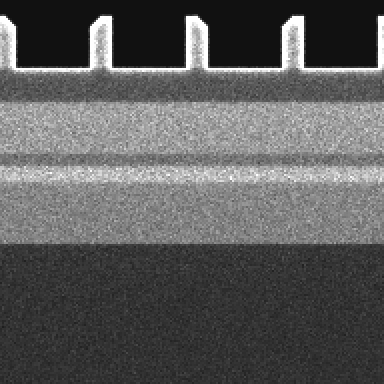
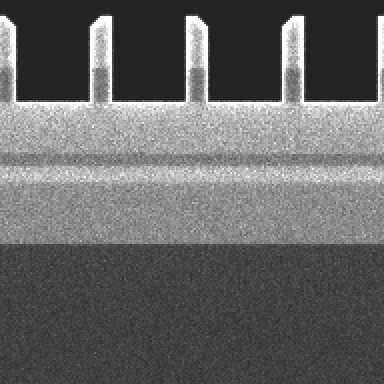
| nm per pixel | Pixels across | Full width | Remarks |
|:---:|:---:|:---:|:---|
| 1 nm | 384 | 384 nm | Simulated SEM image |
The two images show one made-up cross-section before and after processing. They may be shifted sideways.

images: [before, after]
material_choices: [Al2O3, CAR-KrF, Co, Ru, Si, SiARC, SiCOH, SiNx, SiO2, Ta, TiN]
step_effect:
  removed: SiNx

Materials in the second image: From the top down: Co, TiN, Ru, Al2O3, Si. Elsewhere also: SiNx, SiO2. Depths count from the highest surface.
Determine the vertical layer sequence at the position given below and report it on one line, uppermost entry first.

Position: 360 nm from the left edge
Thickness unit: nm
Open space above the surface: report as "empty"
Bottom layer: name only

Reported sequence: empty 86, Co 52, TiN 12, Ru 16, Al2O3 62, Si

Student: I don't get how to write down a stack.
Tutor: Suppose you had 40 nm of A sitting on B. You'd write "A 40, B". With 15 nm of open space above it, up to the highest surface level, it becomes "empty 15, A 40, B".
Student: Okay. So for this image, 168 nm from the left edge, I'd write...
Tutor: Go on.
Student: empty 86, Co 52, TiN 12, Ru 16, Al2O3 62, Si